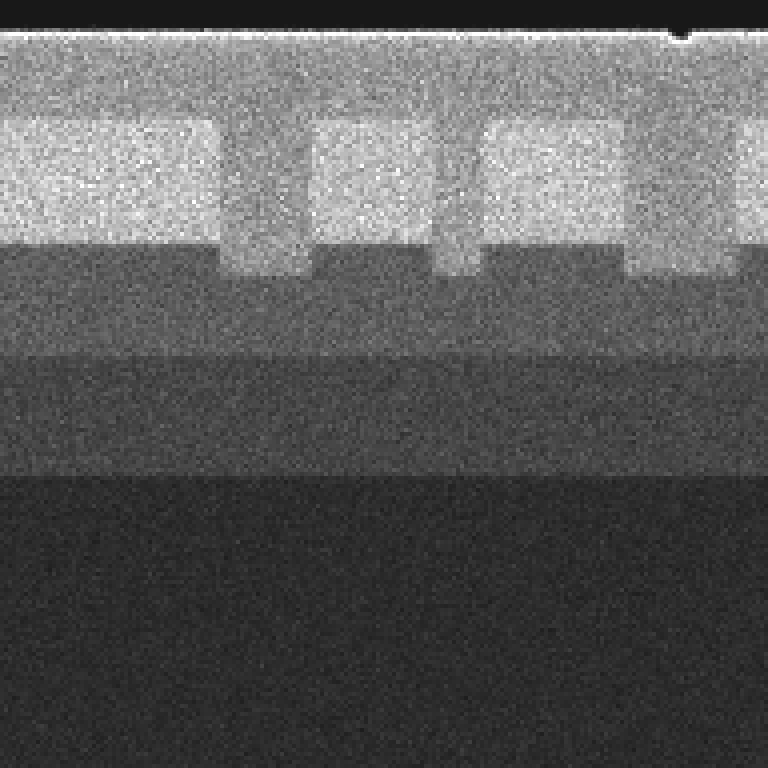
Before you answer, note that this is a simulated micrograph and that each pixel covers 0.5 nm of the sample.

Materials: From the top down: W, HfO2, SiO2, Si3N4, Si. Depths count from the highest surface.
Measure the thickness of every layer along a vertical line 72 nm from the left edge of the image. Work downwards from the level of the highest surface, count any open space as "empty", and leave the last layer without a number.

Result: W 44, HfO2 62, SiO2 56, Si3N4 60, Si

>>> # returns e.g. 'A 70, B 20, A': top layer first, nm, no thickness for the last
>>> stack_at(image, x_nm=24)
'W 44, HfO2 62, SiO2 56, Si3N4 60, Si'